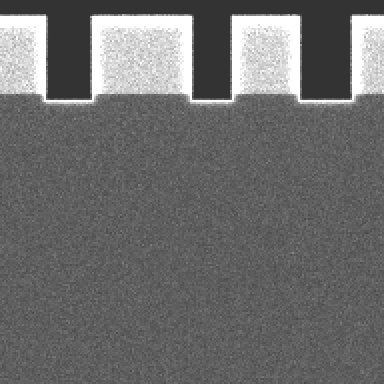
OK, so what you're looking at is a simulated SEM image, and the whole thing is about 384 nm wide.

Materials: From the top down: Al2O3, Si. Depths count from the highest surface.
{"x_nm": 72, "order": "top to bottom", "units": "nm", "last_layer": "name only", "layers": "empty 84, Si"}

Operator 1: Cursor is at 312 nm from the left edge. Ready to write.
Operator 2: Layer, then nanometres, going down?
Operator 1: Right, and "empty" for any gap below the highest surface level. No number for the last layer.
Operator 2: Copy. empty 84, Si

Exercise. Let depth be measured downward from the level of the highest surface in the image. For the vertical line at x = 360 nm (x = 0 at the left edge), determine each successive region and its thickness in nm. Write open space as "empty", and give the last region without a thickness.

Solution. Al2O3 78, Si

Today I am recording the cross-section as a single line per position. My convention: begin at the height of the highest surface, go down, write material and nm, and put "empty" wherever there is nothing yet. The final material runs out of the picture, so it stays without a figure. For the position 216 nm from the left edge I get empty 84, Si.